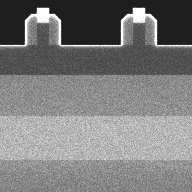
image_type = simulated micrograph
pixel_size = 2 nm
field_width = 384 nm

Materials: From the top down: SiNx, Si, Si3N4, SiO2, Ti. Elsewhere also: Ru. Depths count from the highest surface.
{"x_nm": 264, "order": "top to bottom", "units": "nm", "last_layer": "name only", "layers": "empty 12, SiNx 62, Si 60, Si3N4 82, SiO2 88, Ti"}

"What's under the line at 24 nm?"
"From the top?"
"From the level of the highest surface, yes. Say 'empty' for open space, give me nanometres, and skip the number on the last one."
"empty 74, Si 60, Si3N4 82, SiO2 88, Ti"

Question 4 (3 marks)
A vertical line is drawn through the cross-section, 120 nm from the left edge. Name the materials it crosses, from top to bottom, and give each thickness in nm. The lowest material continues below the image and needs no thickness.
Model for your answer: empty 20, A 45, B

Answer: empty 24, SiNx 50, Si 60, Si3N4 82, SiO2 88, Ti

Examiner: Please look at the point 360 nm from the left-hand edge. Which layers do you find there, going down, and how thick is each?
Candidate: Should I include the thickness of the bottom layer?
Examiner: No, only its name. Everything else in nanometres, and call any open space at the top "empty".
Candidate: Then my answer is empty 74, Si 60, Si3N4 82, SiO2 88, Ti